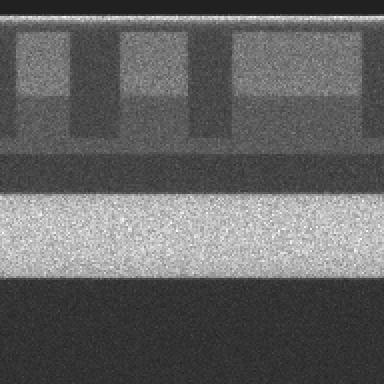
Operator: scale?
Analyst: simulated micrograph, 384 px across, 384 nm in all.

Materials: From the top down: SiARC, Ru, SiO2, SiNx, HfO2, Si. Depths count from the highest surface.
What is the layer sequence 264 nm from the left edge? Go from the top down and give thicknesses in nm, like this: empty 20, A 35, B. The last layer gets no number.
SiARC 16, Ru 64, SiO2 58, SiNx 40, HfO2 84, Si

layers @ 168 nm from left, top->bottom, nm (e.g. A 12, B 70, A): SiARC 16, Ru 64, SiO2 58, SiNx 40, HfO2 84, Si